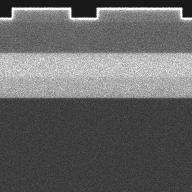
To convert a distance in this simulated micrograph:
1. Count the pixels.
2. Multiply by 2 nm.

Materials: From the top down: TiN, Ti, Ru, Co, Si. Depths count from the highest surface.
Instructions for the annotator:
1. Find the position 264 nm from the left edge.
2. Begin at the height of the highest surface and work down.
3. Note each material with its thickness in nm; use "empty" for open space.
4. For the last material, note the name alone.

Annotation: TiN 28, Ti 62, Ru 48, Co 42, Si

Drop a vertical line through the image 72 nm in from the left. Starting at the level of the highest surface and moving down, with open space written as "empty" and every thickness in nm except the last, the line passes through TiN 28, Ti 62, Ru 48, Co 42, Si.